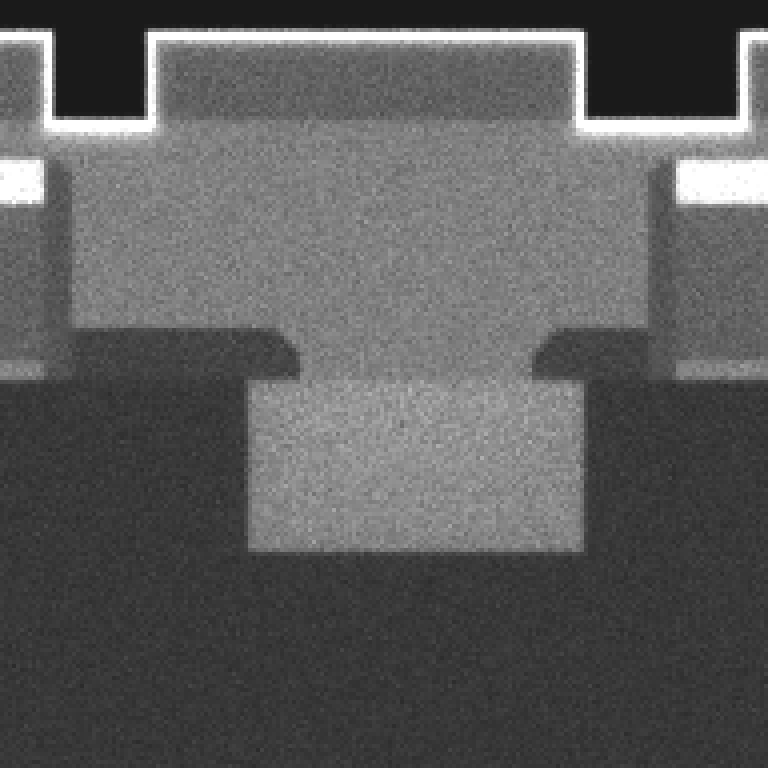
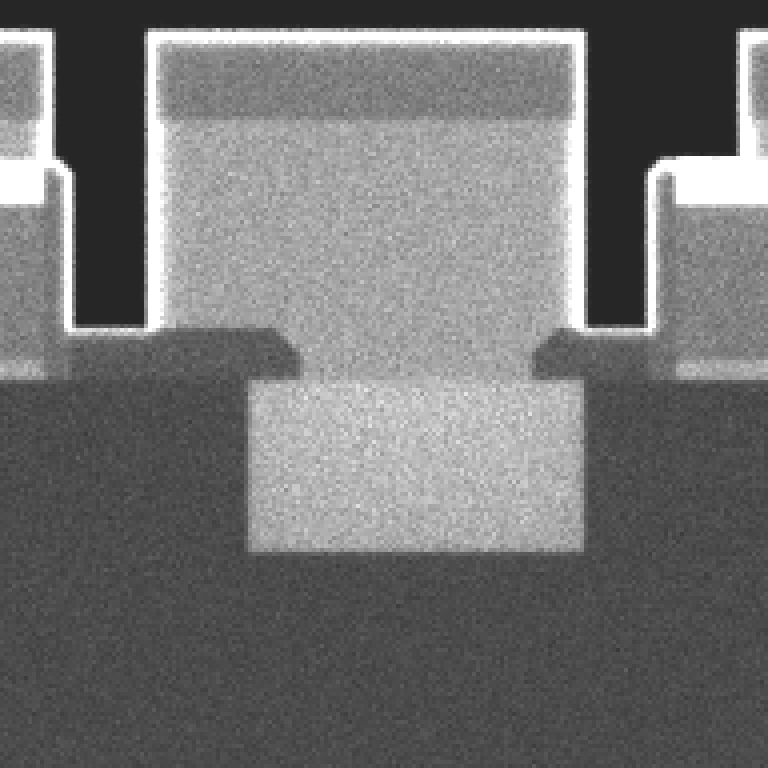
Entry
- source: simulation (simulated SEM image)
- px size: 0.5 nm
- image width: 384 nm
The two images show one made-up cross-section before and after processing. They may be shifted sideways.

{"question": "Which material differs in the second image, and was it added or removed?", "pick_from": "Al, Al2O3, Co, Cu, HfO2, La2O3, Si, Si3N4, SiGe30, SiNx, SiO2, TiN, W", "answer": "SiO2, removed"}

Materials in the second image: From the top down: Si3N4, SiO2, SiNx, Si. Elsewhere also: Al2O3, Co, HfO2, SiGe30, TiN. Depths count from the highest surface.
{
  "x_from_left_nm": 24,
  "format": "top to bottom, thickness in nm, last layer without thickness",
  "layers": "Si3N4 44, SiO2 20, SiNx 110, Si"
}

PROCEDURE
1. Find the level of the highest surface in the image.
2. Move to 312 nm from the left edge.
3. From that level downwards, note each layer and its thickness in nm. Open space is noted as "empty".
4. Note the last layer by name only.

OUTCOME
empty 148, SiGe30 26, Si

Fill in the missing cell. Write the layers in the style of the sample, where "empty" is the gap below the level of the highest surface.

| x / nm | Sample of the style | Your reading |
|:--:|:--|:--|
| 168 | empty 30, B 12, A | Si3N4 44, SiO2 130, Co 86, Si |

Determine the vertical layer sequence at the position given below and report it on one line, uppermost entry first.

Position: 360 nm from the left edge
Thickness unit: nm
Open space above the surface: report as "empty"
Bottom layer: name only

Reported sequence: empty 64, HfO2 22, TiN 78, Al2O3 10, Si